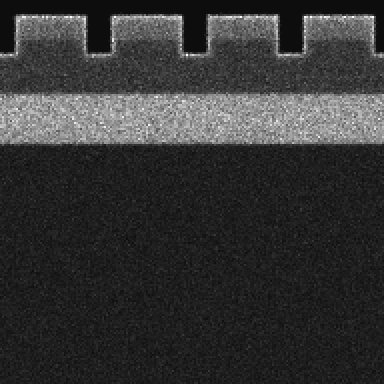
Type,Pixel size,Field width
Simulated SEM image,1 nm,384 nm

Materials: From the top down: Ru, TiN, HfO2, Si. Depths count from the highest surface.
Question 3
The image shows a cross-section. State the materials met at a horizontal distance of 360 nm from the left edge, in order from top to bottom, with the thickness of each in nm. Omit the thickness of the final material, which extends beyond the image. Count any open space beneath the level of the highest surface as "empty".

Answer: Ru 24, TiN 54, HfO2 50, Si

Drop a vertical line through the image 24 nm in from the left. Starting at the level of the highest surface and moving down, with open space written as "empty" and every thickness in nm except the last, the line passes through Ru 24, TiN 54, HfO2 50, Si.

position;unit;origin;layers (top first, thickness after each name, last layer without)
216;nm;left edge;Ru 24, TiN 54, HfO2 50, Si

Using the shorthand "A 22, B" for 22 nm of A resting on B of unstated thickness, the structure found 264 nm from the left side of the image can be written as Ru 24, TiN 54, HfO2 50, Si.